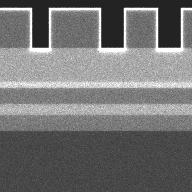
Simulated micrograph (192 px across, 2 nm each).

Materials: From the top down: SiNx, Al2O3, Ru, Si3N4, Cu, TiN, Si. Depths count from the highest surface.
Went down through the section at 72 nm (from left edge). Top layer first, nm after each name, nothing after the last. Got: empty 80, Al2O3 68, Ru 12, Si3N4 32, Cu 22, TiN 32, Si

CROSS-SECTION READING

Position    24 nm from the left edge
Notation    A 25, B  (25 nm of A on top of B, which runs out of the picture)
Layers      SiNx 80, Al2O3 68, Ru 12, Si3N4 32, Cu 22, TiN 32, Si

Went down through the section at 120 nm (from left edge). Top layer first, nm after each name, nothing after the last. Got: SiNx 80, Al2O3 68, Ru 12, Si3N4 32, Cu 22, TiN 32, Si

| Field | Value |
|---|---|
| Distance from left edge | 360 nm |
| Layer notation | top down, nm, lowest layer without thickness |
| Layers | empty 80, Al2O3 68, Ru 12, Si3N4 32, Cu 22, TiN 32, Si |